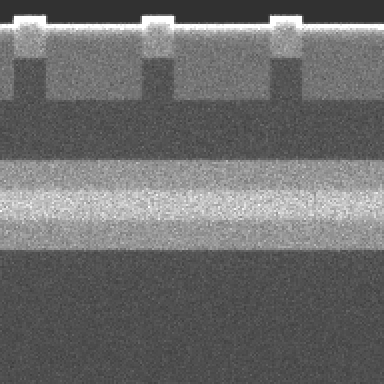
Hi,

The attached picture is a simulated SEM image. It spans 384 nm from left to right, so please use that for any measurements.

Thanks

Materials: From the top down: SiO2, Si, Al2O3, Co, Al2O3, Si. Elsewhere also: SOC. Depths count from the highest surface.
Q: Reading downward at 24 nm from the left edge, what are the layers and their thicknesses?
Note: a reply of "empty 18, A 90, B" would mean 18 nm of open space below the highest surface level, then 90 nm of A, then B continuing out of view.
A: SiO2 42, Si 102, Al2O3 30, Co 30, Al2O3 30, Si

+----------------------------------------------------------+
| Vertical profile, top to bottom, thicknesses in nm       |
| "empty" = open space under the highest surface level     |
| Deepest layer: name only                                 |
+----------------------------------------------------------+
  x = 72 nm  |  empty 8, SOC 76, Si 60, Al2O3 30, Co 30, Al2O3 30, Si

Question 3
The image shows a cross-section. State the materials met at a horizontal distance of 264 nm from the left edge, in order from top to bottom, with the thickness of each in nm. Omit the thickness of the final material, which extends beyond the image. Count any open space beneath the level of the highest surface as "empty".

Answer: empty 8, SOC 76, Si 60, Al2O3 30, Co 30, Al2O3 30, Si